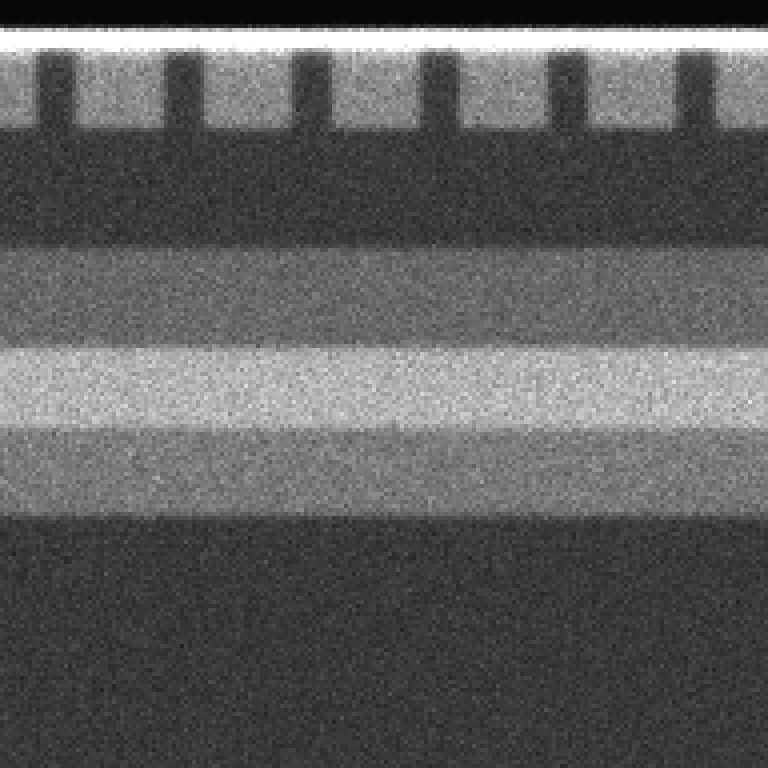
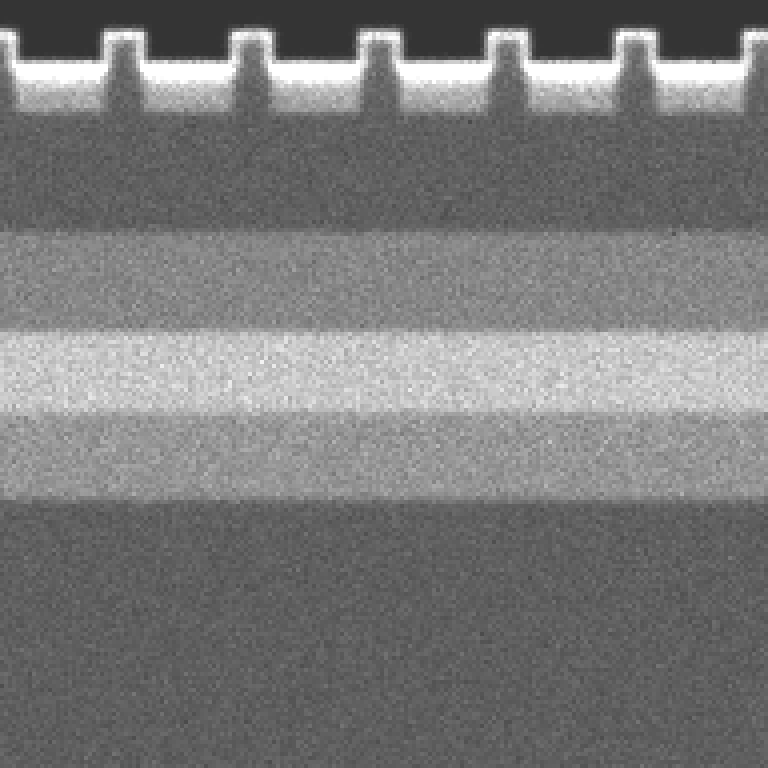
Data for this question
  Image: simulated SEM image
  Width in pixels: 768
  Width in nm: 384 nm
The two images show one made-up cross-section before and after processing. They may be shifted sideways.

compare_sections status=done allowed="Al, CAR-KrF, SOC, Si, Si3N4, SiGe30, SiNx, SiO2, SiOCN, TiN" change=removed material="SOC"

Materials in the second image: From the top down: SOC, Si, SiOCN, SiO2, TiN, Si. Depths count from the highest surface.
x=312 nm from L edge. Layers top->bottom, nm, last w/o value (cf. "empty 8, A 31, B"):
Si 100, SiOCN 50, SiO2 40, TiN 44, Si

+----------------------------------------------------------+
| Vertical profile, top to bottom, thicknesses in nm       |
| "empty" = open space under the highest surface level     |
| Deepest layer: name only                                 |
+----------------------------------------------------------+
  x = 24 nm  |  empty 16, SOC 24, Si 60, SiOCN 50, SiO2 40, TiN 44, Si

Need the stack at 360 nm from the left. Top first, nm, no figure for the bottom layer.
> empty 16, SOC 24, Si 60, SiOCN 50, SiO2 40, TiN 44, Si